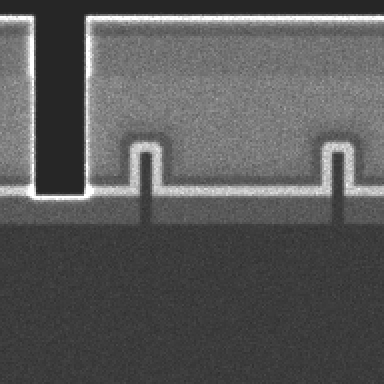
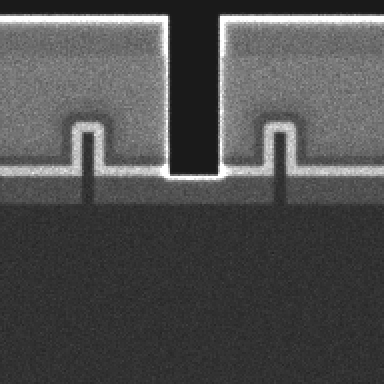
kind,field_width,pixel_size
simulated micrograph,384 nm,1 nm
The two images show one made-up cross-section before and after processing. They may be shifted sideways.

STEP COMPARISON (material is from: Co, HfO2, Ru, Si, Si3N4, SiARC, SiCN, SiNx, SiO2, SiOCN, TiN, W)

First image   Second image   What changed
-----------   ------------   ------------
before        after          SiARC, removed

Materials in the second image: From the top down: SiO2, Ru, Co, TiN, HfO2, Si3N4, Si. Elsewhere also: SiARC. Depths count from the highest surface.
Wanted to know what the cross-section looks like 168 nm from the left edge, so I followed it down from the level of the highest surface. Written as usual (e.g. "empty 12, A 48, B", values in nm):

empty 160, Si3N4 28, Si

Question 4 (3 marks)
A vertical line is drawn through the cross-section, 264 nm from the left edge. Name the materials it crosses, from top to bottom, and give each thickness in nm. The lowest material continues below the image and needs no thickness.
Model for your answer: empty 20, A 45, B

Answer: SiO2 40, Ru 44, Co 12, TiN 14, HfO2 50, Si3N4 28, Si